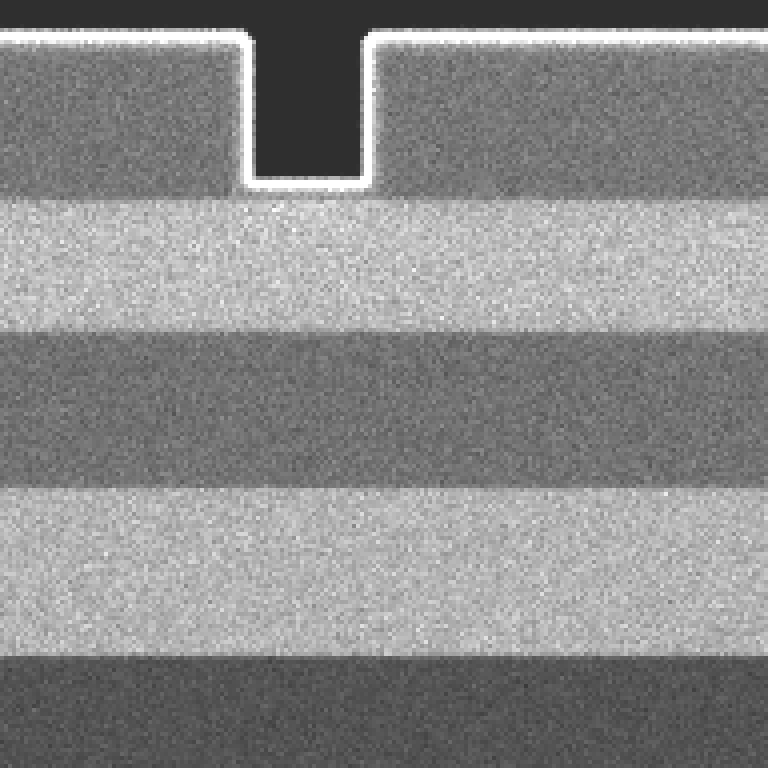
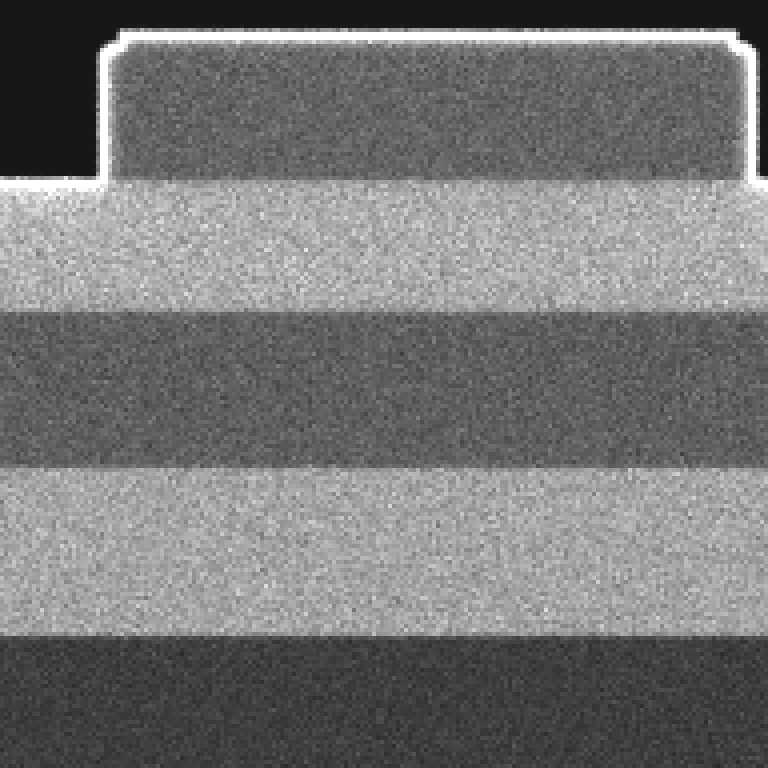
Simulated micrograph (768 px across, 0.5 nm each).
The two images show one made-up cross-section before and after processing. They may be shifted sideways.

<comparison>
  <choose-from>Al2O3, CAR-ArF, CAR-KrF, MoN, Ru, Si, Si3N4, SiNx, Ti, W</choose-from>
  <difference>Si3N4 removed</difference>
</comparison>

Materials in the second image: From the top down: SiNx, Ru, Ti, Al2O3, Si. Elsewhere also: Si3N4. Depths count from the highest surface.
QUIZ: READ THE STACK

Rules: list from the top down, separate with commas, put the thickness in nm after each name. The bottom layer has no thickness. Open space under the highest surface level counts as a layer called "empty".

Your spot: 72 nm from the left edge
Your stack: SiNx 74, Ru 66, Ti 78, Al2O3 84, Si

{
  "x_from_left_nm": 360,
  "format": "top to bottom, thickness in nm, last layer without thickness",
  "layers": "SiNx 74, Ru 66, Ti 78, Al2O3 84, Si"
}